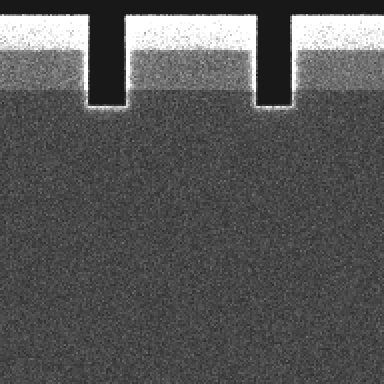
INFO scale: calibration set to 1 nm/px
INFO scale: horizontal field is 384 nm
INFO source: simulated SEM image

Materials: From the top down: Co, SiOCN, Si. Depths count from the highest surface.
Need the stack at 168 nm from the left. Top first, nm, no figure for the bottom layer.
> Co 34, SiOCN 40, Si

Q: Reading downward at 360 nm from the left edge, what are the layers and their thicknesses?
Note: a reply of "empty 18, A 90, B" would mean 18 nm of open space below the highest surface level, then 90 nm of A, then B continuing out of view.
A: Co 34, SiOCN 40, Si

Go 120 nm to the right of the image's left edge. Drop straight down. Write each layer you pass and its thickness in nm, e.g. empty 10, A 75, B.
empty 90, Si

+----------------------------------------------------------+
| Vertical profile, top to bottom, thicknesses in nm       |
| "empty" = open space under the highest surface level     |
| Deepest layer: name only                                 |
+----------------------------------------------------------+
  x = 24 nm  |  Co 34, SiOCN 40, Si